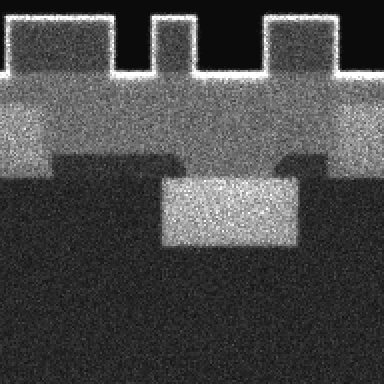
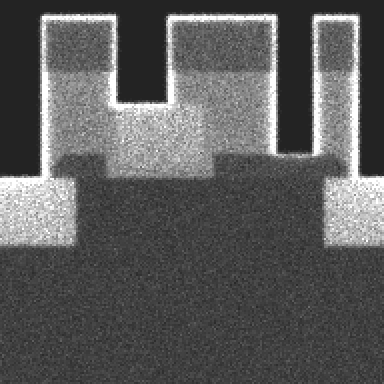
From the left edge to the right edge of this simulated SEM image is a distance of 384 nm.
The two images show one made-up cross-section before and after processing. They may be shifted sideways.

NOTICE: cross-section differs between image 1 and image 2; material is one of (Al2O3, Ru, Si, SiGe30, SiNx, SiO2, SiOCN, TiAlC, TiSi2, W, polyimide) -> removed: SiO2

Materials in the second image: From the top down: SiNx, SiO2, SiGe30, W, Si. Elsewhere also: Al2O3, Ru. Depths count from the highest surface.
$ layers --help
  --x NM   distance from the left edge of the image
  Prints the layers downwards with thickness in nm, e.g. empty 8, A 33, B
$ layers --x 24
empty 162, W 68, Si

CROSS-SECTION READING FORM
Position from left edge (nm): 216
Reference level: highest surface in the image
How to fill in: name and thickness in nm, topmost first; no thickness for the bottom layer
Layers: SiNx 56, SiO2 82, SiGe30 24, Si